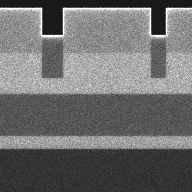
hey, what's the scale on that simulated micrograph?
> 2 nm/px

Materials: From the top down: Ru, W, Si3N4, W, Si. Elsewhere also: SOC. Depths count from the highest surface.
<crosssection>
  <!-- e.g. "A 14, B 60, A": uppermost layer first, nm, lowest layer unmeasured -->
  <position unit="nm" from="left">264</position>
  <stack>Ru 90, W 82, Si3N4 84, W 26, Si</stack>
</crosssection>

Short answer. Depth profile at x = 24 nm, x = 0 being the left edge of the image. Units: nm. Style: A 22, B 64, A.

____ Ru 90, W 82, Si3N4 84, W 26, Si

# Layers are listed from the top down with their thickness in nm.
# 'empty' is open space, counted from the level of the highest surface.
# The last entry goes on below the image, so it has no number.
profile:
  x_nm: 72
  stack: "Ru 90, W 82, Si3N4 84, W 26, Si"